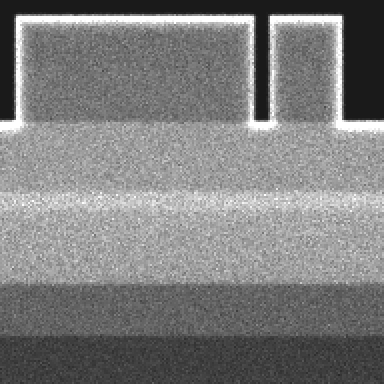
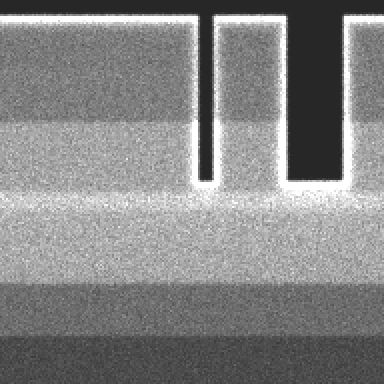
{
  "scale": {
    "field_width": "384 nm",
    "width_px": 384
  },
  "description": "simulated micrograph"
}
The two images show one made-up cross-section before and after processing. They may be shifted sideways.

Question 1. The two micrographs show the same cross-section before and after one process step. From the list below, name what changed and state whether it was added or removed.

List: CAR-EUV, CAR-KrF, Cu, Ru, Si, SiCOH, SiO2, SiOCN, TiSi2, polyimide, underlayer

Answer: SiO2, removed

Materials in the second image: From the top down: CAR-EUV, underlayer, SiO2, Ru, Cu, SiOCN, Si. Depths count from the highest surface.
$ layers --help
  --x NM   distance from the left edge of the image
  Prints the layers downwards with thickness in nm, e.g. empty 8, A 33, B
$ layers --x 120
CAR-EUV 52, underlayer 54, SiO2 70, Ru 18, Cu 74, SiOCN 52, Si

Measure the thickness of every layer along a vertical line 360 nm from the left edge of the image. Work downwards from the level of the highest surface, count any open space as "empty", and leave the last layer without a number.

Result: CAR-EUV 52, underlayer 54, SiO2 70, Ru 18, Cu 74, SiOCN 52, Si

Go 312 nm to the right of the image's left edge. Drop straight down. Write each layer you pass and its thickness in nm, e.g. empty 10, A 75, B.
empty 166, SiO2 10, Ru 18, Cu 74, SiOCN 52, Si